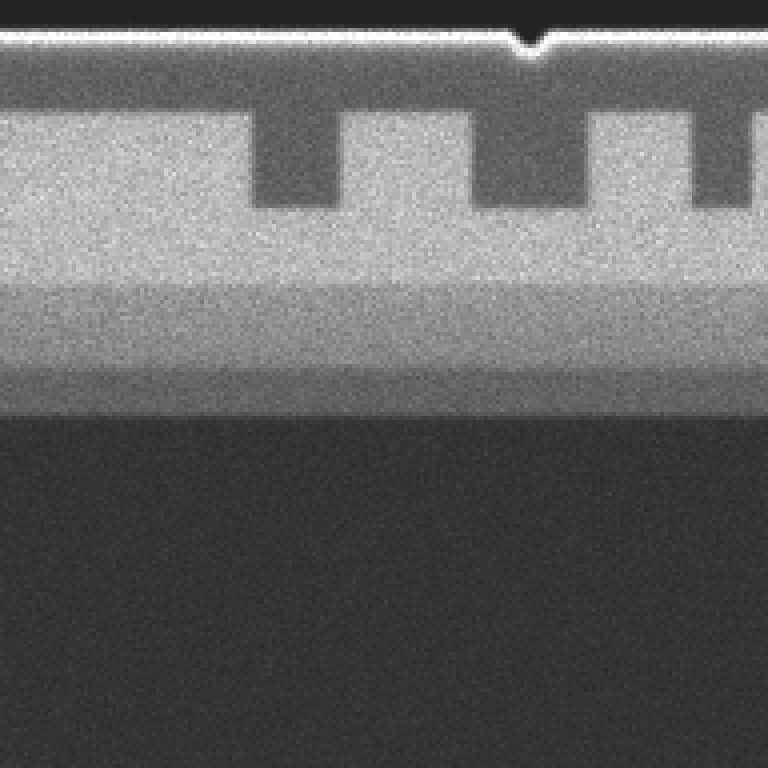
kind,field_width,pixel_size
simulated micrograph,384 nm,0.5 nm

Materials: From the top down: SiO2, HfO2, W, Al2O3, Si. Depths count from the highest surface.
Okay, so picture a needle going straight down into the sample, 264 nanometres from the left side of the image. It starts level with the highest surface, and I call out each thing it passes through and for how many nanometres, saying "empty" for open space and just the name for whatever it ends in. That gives empty 8, SiO2 80, HfO2 38, W 42, Al2O3 24, Si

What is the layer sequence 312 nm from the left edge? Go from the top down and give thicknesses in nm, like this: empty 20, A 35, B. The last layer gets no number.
SiO2 40, HfO2 86, W 42, Al2O3 24, Si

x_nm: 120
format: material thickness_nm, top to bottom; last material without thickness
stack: SiO2 40, HfO2 86, W 42, Al2O3 24, Si